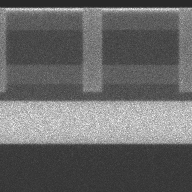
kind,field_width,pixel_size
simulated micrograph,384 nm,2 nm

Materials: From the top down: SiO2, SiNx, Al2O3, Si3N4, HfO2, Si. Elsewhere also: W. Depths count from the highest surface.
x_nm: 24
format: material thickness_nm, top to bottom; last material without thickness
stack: SiO2 44, SiNx 70, Al2O3 38, Si3N4 34, HfO2 86, Si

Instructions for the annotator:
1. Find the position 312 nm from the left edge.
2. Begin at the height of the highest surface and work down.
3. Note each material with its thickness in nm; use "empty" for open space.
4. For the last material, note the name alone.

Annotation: SiO2 44, SiNx 70, Al2O3 38, Si3N4 34, HfO2 86, Si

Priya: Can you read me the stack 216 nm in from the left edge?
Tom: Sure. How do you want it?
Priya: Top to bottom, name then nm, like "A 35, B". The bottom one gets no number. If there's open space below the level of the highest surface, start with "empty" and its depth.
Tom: SiO2 44, SiNx 70, Al2O3 38, Si3N4 34, HfO2 86, Si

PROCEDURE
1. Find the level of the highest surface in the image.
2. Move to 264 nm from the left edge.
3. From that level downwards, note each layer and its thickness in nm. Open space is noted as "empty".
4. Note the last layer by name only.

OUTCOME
SiO2 44, SiNx 70, Al2O3 38, Si3N4 34, HfO2 86, Si